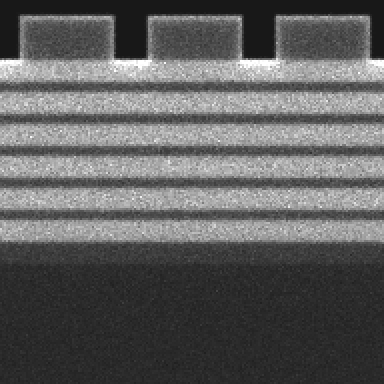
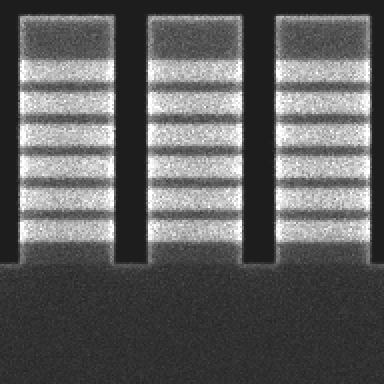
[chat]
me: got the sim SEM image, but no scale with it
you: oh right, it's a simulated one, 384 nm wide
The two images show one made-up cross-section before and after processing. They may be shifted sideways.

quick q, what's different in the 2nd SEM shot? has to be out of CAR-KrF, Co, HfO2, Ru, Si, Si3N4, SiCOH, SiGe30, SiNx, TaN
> HfO2 and SiNx removed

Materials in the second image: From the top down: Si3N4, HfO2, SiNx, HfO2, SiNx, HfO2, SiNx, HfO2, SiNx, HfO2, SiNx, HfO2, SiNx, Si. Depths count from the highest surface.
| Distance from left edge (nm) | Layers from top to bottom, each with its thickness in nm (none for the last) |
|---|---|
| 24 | Si3N4 44, HfO2 22, SiNx 10, HfO2 22, SiNx 10, HfO2 22, SiNx 10, HfO2 22, SiNx 10, HfO2 22, SiNx 10, HfO2 22, SiNx 22, Si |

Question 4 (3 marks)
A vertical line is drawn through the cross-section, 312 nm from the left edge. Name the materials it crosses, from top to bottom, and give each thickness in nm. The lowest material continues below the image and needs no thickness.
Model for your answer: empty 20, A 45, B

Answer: Si3N4 44, HfO2 22, SiNx 10, HfO2 22, SiNx 10, HfO2 22, SiNx 10, HfO2 22, SiNx 10, HfO2 22, SiNx 10, HfO2 22, SiNx 22, Si